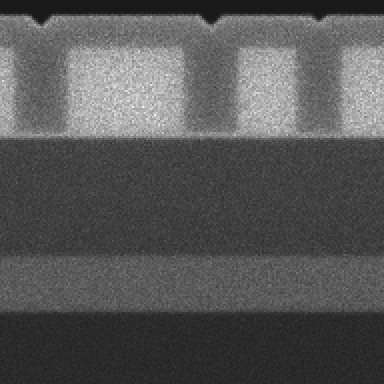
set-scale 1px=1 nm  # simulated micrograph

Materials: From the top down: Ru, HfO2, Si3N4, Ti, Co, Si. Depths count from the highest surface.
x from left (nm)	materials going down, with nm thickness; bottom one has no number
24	Ru 116, HfO2 6, Si3N4 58, Ti 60, Co 56, Si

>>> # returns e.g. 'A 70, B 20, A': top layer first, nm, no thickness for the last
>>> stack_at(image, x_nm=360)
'Ru 32, HfO2 90, Si3N4 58, Ti 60, Co 56, Si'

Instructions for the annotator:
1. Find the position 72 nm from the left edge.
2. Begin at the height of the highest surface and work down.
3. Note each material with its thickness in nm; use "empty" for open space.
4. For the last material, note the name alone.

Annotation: Ru 32, HfO2 90, Si3N4 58, Ti 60, Co 56, Si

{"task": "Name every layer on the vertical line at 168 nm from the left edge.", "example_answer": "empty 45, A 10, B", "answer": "Ru 32, HfO2 90, Si3N4 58, Ti 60, Co 56, Si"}